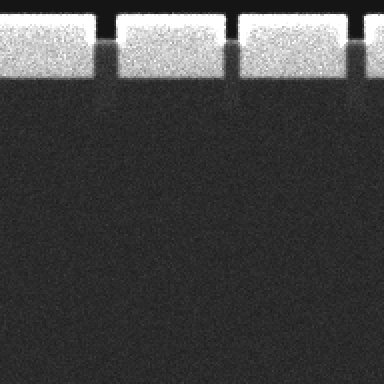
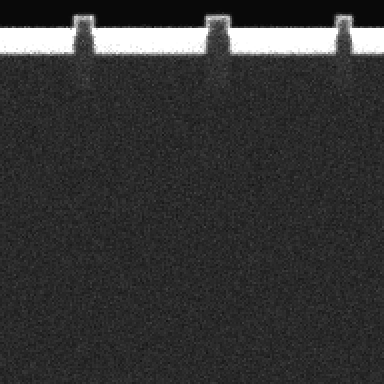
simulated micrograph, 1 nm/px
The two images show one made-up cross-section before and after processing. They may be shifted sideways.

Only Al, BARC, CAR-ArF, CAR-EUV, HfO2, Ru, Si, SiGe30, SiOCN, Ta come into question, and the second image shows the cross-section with HfO2 removed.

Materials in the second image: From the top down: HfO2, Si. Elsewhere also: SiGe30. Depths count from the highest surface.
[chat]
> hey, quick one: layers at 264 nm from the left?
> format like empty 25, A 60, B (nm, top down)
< empty 14, HfO2 24, Si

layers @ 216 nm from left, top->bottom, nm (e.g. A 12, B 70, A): SiGe30 72, Si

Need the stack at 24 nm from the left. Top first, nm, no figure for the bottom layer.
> empty 14, HfO2 24, Si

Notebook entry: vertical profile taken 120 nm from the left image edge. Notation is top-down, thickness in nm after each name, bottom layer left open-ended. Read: empty 14, HfO2 24, Si